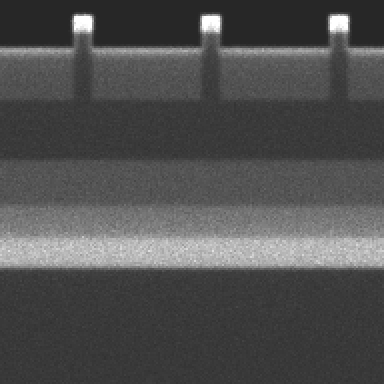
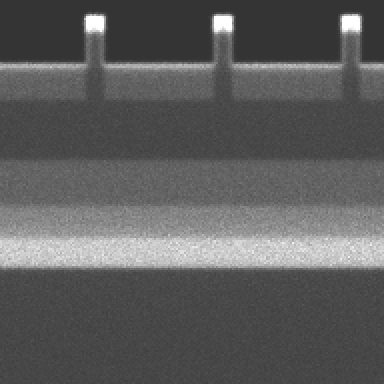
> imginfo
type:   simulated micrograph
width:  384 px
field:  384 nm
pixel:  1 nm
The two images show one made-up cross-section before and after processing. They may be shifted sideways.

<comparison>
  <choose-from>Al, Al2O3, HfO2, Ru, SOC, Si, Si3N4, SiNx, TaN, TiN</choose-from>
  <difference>SOC removed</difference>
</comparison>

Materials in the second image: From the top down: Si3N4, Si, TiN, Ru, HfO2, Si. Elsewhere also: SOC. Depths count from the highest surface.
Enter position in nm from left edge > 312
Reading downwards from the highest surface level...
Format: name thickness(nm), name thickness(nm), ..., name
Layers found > empty 48, Si3N4 36, Si 60, TiN 46, Ru 32, HfO2 30, Si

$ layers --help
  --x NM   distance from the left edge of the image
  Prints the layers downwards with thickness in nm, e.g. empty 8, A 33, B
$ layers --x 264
empty 48, Si3N4 36, Si 60, TiN 46, Ru 32, HfO2 30, Si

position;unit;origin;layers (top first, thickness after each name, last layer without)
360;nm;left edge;empty 48, Si3N4 36, Si 60, TiN 46, Ru 32, HfO2 30, Si